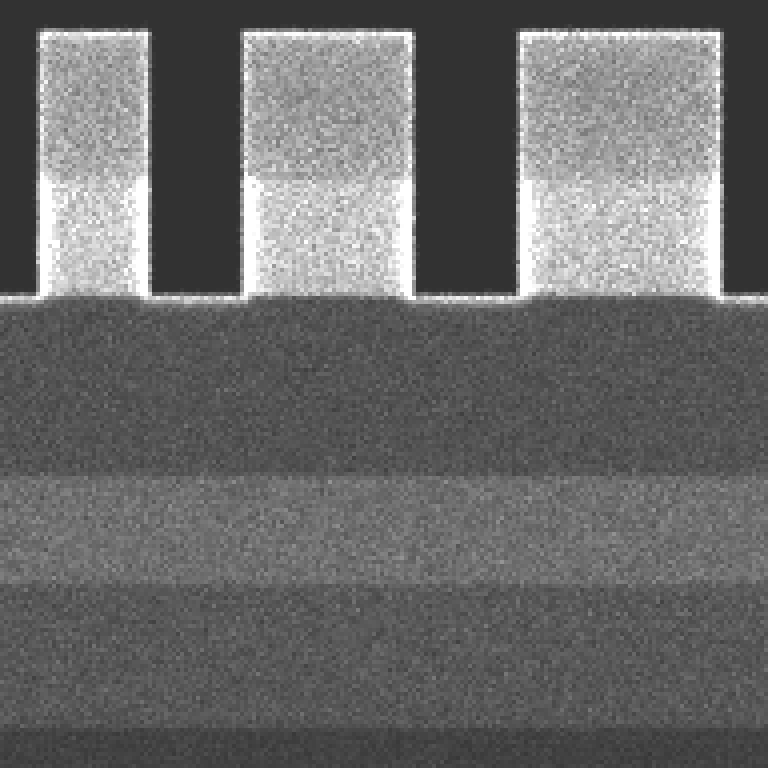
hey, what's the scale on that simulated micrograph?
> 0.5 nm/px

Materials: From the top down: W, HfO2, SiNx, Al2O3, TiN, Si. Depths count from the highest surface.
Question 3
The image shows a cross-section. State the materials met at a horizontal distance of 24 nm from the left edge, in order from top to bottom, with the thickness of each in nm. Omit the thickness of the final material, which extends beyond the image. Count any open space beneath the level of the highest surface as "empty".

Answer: W 74, HfO2 58, SiNx 90, Al2O3 54, TiN 72, Si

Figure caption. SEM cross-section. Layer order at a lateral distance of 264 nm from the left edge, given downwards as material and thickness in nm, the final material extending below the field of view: W 74, HfO2 58, SiNx 90, Al2O3 54, TiN 72, Si